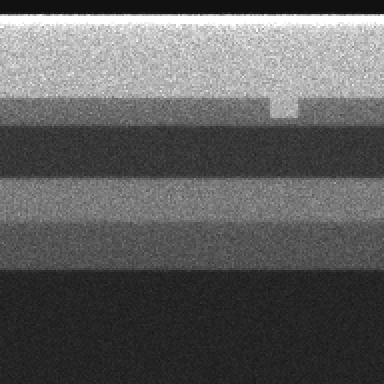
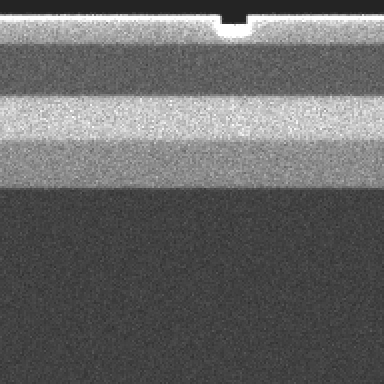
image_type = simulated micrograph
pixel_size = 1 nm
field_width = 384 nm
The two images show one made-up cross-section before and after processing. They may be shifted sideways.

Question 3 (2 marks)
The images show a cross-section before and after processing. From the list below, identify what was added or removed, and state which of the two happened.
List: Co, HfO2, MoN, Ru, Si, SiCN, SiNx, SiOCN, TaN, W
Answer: HfO2 was removed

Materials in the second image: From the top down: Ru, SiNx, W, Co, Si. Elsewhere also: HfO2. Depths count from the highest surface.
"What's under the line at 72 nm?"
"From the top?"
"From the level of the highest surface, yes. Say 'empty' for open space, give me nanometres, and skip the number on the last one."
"Ru 28, SiNx 52, W 44, Co 48, Si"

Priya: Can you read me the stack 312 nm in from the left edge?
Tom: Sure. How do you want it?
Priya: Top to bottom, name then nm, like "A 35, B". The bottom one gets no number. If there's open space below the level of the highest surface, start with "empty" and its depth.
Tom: Ru 28, SiNx 52, W 44, Co 48, Si